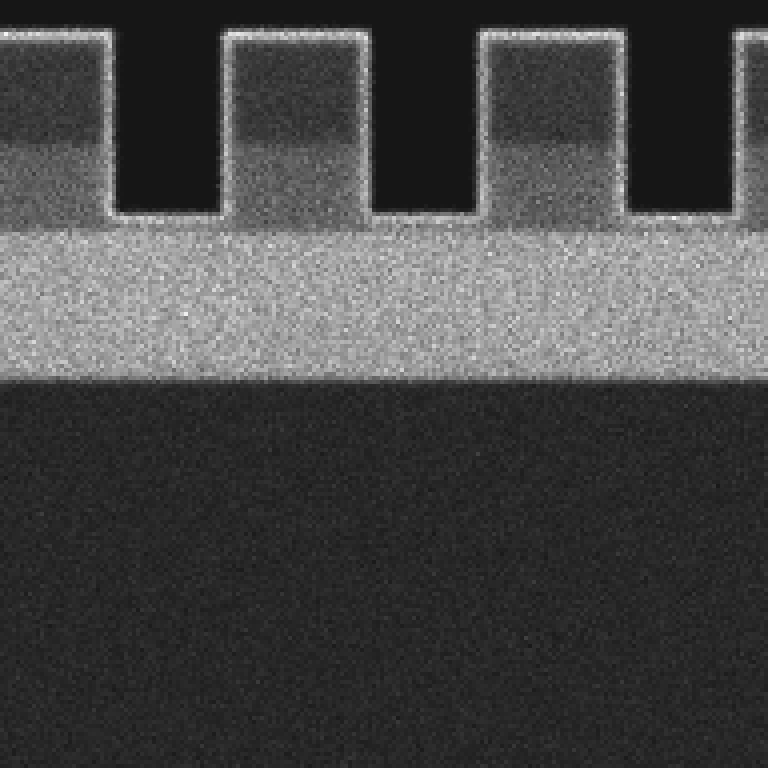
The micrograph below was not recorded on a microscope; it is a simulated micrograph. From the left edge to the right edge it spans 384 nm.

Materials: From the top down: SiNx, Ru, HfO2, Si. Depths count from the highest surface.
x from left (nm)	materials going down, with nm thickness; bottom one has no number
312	empty 92, Ru 8, HfO2 74, Si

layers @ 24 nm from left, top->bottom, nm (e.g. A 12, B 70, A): SiNx 56, Ru 44, HfO2 74, Si